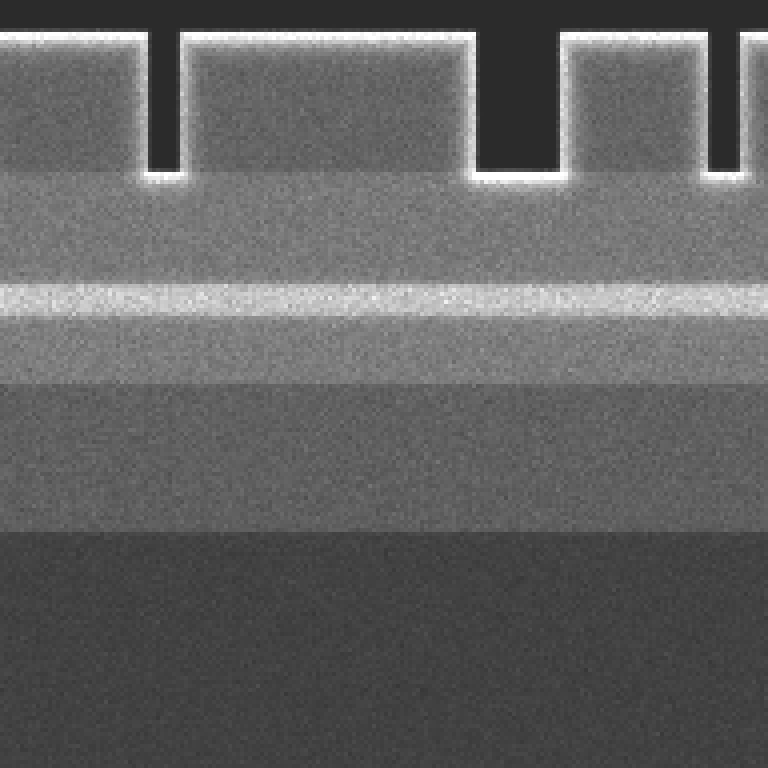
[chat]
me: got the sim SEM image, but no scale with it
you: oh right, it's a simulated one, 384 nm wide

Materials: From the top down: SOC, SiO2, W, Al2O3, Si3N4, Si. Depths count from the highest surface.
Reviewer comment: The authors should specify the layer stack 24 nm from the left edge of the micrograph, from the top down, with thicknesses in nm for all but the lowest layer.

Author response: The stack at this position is SOC 70, SiO2 56, W 16, Al2O3 34, Si3N4 74, Si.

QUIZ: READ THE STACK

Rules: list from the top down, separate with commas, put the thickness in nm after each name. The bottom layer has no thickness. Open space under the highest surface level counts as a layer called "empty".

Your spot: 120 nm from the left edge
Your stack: SOC 70, SiO2 56, W 16, Al2O3 34, Si3N4 74, Si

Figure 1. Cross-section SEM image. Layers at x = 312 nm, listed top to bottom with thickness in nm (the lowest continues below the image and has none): SOC 70, SiO2 56, W 16, Al2O3 34, Si3N4 74, Si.